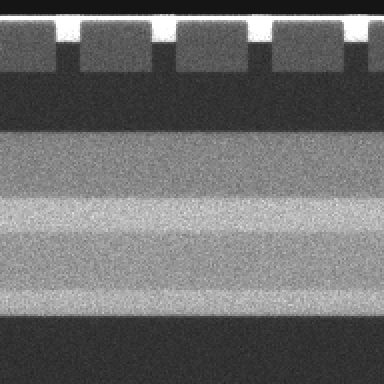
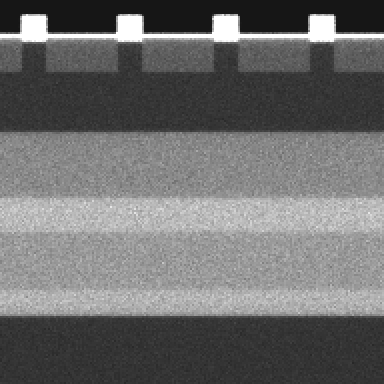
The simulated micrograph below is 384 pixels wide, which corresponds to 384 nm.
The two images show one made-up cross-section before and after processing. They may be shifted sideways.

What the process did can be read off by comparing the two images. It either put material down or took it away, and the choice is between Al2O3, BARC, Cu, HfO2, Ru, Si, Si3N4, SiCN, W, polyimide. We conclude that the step removed Si3N4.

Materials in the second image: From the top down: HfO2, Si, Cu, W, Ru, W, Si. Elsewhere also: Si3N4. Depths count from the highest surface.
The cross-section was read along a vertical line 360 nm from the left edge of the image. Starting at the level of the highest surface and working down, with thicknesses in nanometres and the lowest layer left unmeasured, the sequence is empty 18, Si3N4 38, Si 60, Cu 66, W 34, Ru 58, W 26, Si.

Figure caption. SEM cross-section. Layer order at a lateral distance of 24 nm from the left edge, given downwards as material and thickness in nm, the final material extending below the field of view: HfO2 26, Si 90, Cu 66, W 34, Ru 58, W 26, Si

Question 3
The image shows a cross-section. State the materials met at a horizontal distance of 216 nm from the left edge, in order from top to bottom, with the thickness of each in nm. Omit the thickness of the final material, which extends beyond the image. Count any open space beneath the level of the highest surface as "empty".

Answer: HfO2 26, Si 90, Cu 66, W 34, Ru 58, W 26, Si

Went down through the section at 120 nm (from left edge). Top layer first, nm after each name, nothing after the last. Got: HfO2 26, Si 90, Cu 66, W 34, Ru 58, W 26, Si